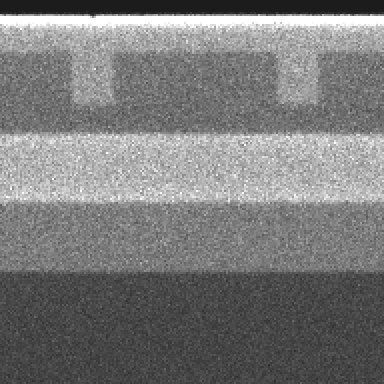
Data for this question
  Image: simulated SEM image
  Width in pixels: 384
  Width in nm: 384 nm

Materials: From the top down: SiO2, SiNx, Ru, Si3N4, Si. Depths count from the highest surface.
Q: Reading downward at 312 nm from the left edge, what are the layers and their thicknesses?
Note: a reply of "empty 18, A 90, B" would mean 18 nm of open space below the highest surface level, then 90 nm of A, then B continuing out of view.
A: SiO2 88, SiNx 30, Ru 68, Si3N4 70, Si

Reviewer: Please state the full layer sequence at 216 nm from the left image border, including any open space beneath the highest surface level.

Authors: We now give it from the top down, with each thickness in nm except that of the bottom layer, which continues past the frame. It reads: SiO2 36, SiNx 82, Ru 68, Si3N4 70, Si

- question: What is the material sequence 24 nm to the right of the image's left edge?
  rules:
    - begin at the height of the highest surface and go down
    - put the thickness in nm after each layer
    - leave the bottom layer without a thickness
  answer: SiO2 36, SiNx 82, Ru 68, Si3N4 70, Si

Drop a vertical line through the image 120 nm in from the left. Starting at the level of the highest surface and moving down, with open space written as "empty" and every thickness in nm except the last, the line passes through SiO2 36, SiNx 82, Ru 68, Si3N4 70, Si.